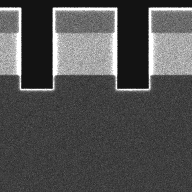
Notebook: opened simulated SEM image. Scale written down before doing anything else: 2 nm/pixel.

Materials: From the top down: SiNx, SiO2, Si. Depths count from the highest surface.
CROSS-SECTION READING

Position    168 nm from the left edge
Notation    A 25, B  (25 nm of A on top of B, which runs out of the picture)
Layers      SiNx 50, SiO2 84, Si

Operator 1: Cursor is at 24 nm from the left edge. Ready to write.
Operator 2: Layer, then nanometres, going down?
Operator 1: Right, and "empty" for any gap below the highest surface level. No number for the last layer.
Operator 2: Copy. SiNx 50, SiO2 84, Si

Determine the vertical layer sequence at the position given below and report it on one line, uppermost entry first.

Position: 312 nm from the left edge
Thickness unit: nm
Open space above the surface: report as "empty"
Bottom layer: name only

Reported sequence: SiNx 50, SiO2 84, Si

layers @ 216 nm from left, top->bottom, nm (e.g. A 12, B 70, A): SiNx 50, SiO2 84, Si